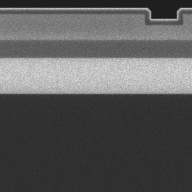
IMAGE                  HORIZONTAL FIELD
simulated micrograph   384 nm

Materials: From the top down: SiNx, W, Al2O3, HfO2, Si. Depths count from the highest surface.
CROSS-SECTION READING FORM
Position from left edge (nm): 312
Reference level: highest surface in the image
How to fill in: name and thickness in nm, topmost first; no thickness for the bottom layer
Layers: empty 22, SiNx 12, W 30, Al2O3 36, HfO2 72, Si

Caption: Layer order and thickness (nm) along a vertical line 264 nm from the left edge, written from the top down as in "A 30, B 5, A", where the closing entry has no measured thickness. SiNx 12, W 52, Al2O3 36, HfO2 72, Si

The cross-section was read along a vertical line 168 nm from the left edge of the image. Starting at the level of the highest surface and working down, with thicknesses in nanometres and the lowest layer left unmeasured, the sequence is SiNx 12, W 52, Al2O3 36, HfO2 72, Si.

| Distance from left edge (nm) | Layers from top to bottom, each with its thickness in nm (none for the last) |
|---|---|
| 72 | SiNx 12, W 52, Al2O3 36, HfO2 72, Si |